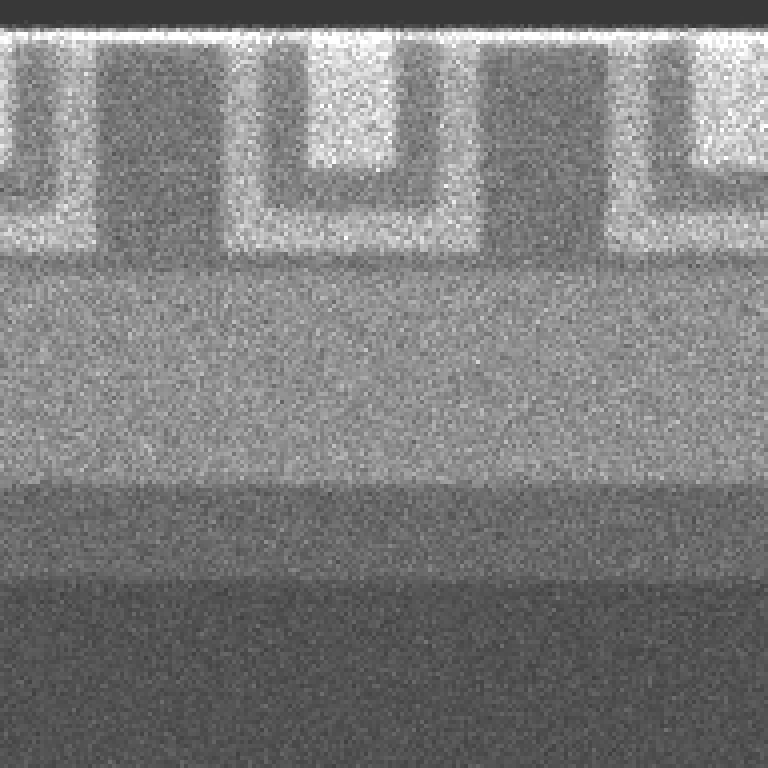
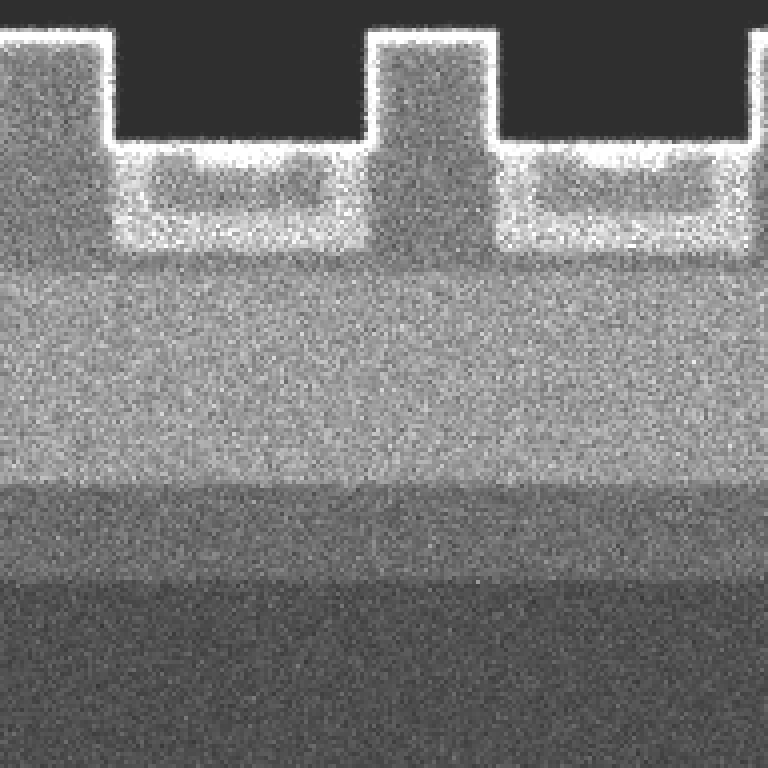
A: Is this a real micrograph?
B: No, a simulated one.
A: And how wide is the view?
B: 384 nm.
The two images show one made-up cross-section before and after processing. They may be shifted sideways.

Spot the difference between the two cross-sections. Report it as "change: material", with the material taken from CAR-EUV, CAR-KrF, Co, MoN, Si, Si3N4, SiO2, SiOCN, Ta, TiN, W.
removed: Co and TiN and W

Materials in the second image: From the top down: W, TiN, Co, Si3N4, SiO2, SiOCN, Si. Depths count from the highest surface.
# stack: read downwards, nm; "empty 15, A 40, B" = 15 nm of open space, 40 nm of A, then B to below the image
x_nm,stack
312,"empty 56, W 12, TiN 22, Co 20, Si3N4 10, SiO2 106, SiOCN 48, Si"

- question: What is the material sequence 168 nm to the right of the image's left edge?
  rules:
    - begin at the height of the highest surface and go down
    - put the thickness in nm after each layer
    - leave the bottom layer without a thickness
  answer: empty 56, Co 54, Si3N4 10, SiO2 106, SiOCN 48, Si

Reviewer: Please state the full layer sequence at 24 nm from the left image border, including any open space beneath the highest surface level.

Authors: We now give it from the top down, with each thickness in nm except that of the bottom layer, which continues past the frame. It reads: Si3N4 120, SiO2 106, SiOCN 48, Si